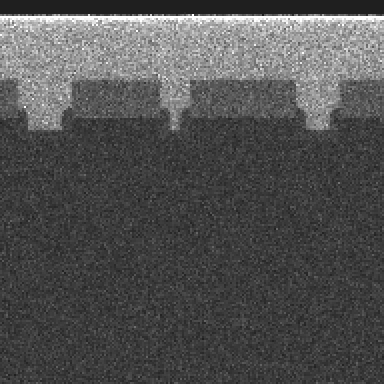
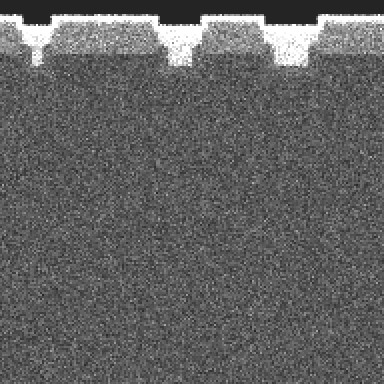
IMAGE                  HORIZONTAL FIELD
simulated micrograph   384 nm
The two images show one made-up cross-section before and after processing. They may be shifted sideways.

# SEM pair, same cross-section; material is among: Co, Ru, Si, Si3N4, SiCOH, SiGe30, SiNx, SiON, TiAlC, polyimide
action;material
removed;Ru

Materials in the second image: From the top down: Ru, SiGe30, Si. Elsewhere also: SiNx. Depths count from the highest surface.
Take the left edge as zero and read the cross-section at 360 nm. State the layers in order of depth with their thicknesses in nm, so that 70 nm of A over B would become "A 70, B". SiNx 38, Si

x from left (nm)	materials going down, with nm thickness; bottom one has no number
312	empty 10, Ru 18, SiGe30 32, Si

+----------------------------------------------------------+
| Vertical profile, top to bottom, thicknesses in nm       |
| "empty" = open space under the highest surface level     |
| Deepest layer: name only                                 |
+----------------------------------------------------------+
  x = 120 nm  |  SiNx 38, Si